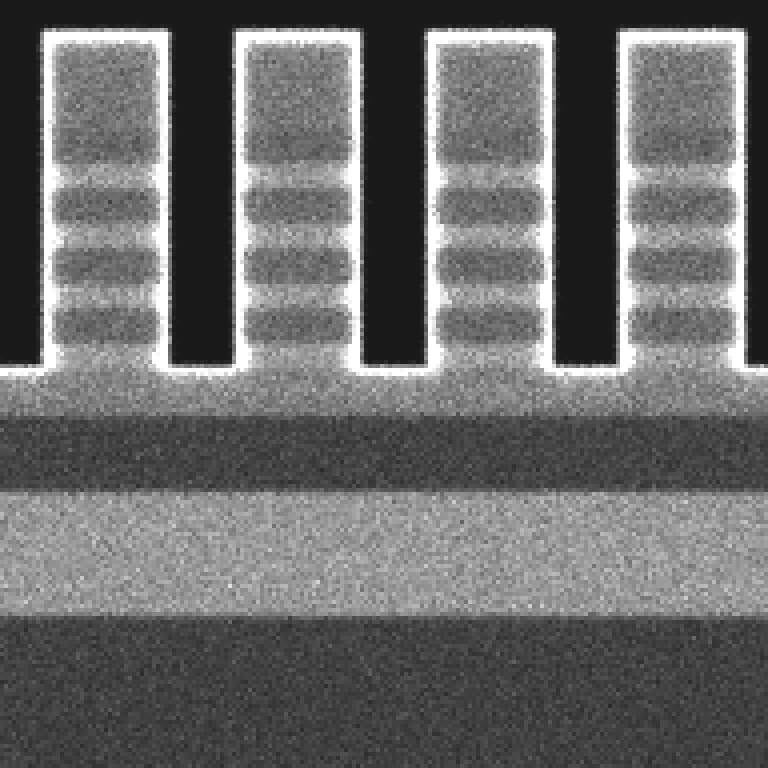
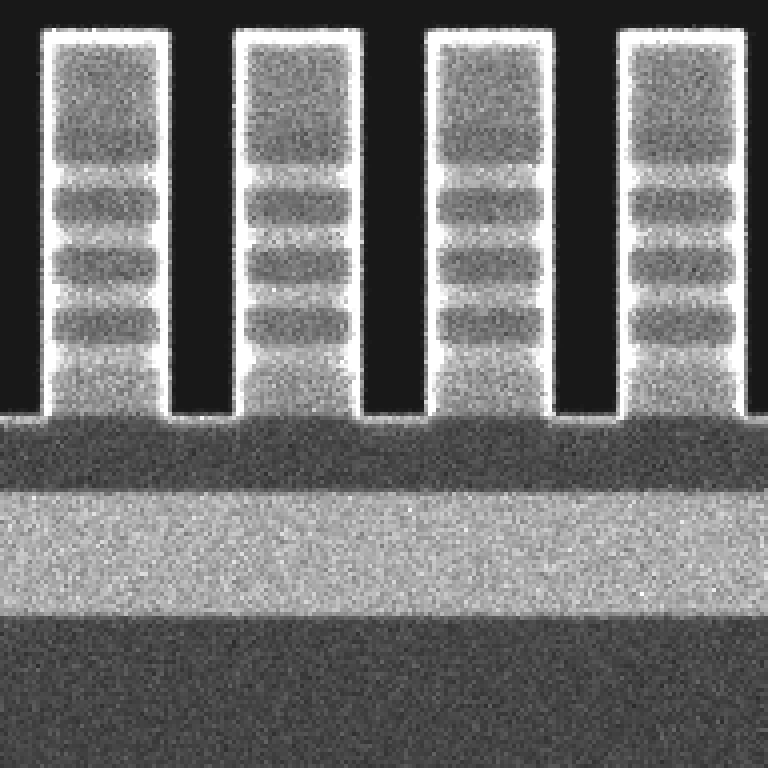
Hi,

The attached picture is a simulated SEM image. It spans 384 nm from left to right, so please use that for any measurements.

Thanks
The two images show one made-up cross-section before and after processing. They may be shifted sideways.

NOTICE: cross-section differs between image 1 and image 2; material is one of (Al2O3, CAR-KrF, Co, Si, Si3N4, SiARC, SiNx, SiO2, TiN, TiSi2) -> removed: TiN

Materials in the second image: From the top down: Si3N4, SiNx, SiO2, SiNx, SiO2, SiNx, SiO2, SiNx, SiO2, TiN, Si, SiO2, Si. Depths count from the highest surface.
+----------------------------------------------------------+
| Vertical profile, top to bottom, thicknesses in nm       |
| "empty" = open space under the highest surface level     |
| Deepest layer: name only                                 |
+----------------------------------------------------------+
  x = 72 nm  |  Si3N4 48, SiNx 18, SiO2 12, SiNx 18, SiO2 12, SiNx 18, SiO2 12, SiNx 18, SiO2 12, TiN 24, Si 38, SiO2 62, Si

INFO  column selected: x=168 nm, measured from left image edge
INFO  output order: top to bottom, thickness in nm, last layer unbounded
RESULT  Si3N4 48, SiNx 18, SiO2 12, SiNx 18, SiO2 12, SiNx 18, SiO2 12, SiNx 18, SiO2 12, TiN 24, Si 38, SiO2 62, Si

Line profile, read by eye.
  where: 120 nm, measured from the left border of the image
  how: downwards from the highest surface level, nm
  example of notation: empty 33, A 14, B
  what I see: Si3N4 48, SiNx 18, SiO2 12, SiNx 18, SiO2 12, SiNx 18, SiO2 12, SiNx 18, SiO2 12, TiN 24, Si 38, SiO2 62, Si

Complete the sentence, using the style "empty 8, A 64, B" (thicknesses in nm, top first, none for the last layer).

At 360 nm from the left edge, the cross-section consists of Si3N4 48, SiNx 18, SiO2 12, SiNx 18, SiO2 12, SiNx 18, SiO2 12, SiNx 18, SiO2 12, TiN 24, Si 38, SiO2 62, Si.